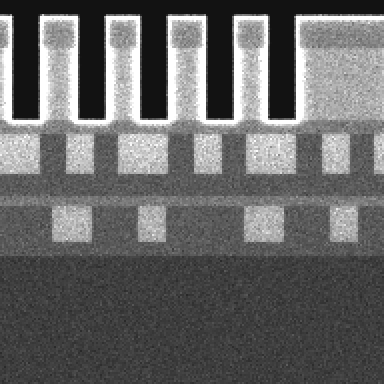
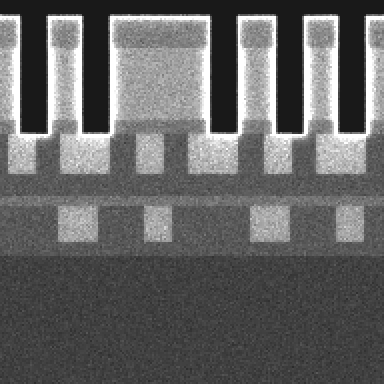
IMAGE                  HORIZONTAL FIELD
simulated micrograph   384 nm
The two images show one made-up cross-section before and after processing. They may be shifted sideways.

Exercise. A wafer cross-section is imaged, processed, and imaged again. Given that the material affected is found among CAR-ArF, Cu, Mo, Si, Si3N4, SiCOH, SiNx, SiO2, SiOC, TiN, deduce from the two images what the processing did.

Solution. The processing removed Si3N4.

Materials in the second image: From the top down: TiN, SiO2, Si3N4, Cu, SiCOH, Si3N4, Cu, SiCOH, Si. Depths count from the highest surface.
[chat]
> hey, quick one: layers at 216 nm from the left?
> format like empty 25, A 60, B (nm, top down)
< empty 118, Cu 40, SiCOH 22, Si3N4 10, SiCOH 50, Si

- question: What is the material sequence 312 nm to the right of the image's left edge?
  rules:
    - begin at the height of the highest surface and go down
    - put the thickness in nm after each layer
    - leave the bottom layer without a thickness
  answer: TiN 32, SiO2 72, Si3N4 14, SiCOH 62, Si3N4 10, SiCOH 50, Si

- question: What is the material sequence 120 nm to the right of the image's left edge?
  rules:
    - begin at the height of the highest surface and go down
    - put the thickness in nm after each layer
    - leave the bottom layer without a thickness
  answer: TiN 32, SiO2 72, Si3N4 14, SiCOH 62, Si3N4 10, SiCOH 50, Si